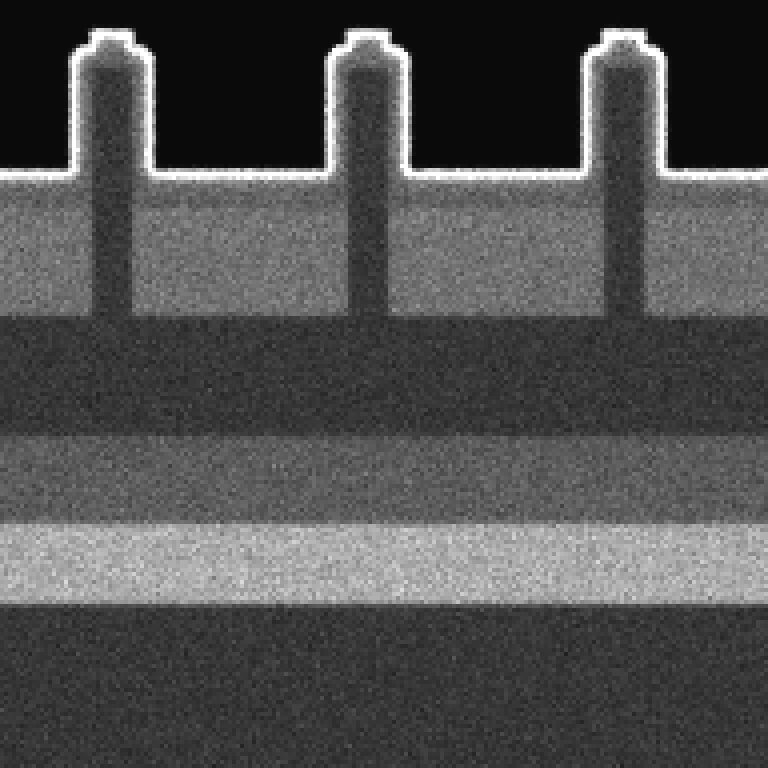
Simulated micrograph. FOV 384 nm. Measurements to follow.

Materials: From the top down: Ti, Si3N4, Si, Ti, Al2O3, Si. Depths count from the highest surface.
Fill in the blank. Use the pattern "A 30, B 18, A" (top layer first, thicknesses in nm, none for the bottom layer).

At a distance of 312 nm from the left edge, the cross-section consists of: Ti 18, Si 184, Ti 44, Al2O3 40, Si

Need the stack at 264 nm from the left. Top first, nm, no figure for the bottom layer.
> empty 70, Ti 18, Si3N4 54, Si 60, Ti 44, Al2O3 40, Si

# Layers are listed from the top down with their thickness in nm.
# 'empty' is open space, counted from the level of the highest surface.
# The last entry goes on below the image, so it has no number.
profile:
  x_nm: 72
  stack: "empty 10, Ti 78, Si3N4 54, Si 60, Ti 44, Al2O3 40, Si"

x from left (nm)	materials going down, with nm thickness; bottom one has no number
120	empty 70, Ti 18, Si3N4 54, Si 60, Ti 44, Al2O3 40, Si